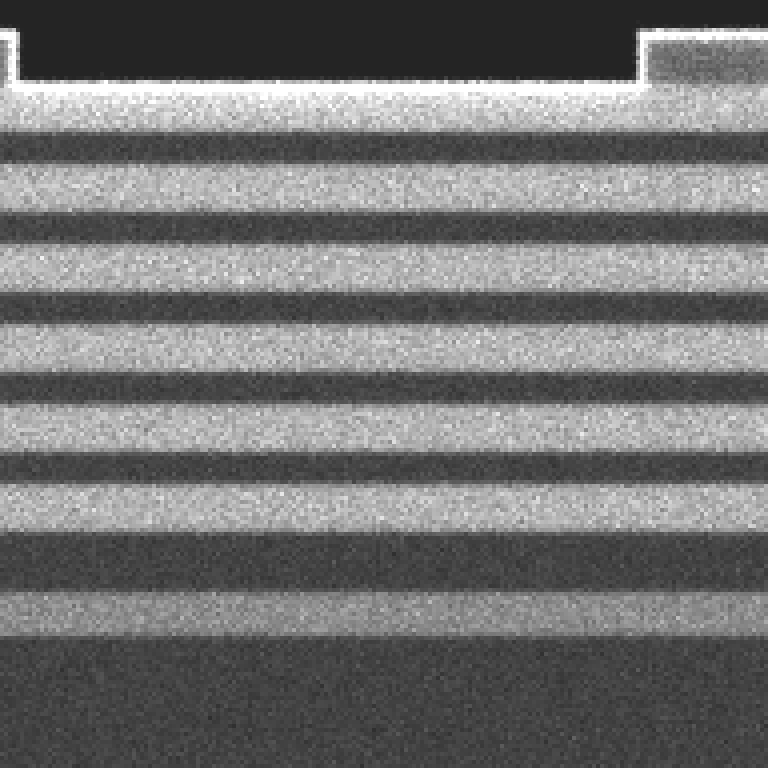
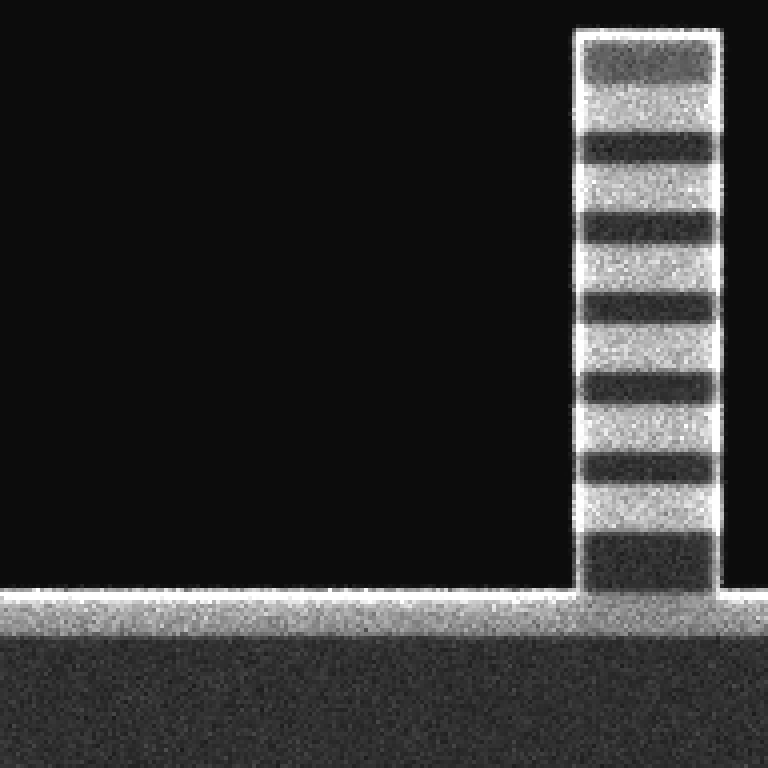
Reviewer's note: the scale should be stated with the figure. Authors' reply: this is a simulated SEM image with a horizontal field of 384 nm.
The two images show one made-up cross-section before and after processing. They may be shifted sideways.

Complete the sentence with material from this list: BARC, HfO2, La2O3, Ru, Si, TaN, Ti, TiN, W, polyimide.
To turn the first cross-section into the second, Si and W must be removed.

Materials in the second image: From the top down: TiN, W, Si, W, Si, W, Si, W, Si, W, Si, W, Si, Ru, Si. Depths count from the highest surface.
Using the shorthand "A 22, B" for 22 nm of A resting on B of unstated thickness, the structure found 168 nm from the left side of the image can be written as empty 280, Ru 22, Si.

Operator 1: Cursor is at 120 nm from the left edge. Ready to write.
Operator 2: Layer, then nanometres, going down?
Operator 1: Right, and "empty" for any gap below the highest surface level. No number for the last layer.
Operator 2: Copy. empty 280, Ru 22, Si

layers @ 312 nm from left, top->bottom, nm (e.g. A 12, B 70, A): TiN 26, W 24, Si 16, W 24, Si 16, W 24, Si 16, W 24, Si 16, W 24, Si 16, W 24, Si 30, Ru 22, Si